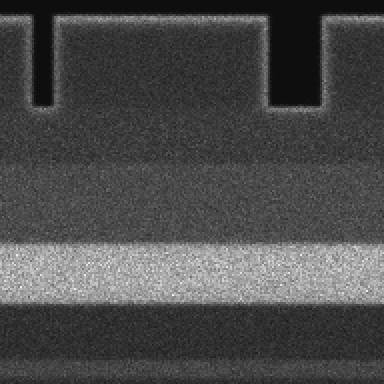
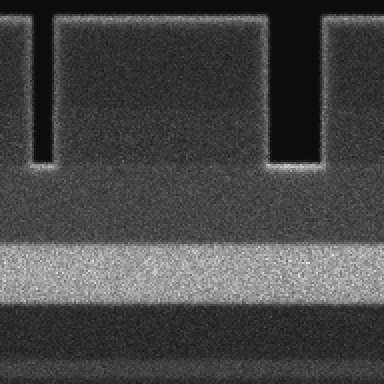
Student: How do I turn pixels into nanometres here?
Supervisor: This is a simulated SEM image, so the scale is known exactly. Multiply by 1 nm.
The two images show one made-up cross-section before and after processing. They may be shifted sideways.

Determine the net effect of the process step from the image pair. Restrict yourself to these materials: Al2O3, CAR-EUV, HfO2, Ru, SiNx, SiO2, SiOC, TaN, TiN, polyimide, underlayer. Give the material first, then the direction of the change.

TiN: removed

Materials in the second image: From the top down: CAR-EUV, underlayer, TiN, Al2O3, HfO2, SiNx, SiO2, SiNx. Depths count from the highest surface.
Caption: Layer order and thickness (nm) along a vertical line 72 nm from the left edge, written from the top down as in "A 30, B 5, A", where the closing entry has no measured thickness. CAR-EUV 70, underlayer 22, TiN 56, Al2O3 80, HfO2 60, SiNx 56, SiO2 18, SiNx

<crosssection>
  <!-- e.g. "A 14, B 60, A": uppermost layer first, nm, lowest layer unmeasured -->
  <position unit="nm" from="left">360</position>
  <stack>CAR-EUV 70, underlayer 22, TiN 56, Al2O3 80, HfO2 60, SiNx 56, SiO2 18, SiNx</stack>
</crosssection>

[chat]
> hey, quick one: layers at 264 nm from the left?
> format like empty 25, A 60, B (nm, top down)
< CAR-EUV 70, underlayer 22, TiN 56, Al2O3 80, HfO2 60, SiNx 56, SiO2 18, SiNx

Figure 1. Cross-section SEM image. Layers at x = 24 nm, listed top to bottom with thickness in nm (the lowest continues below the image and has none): CAR-EUV 70, underlayer 22, TiN 56, Al2O3 80, HfO2 60, SiNx 56, SiO2 18, SiNx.